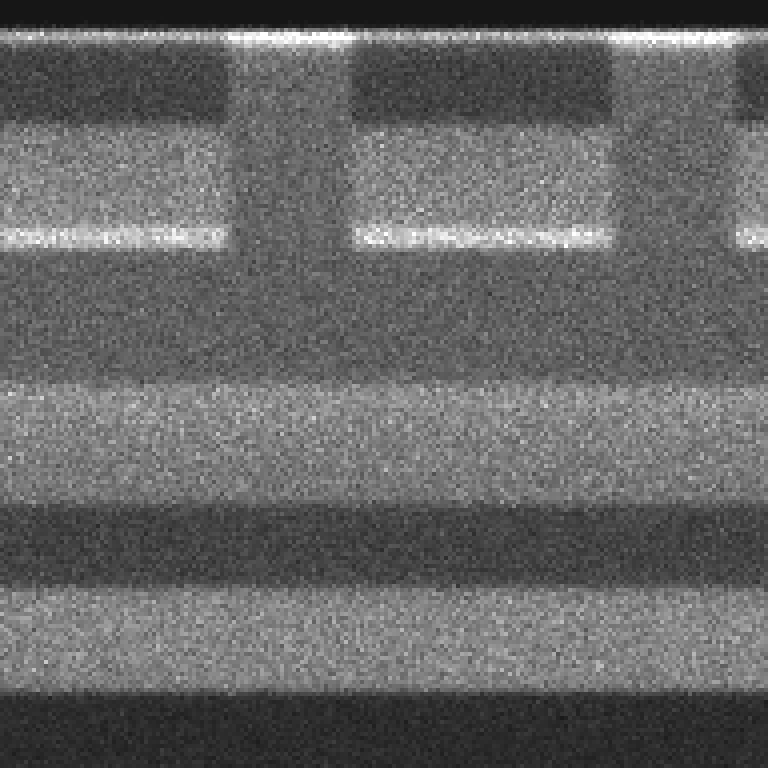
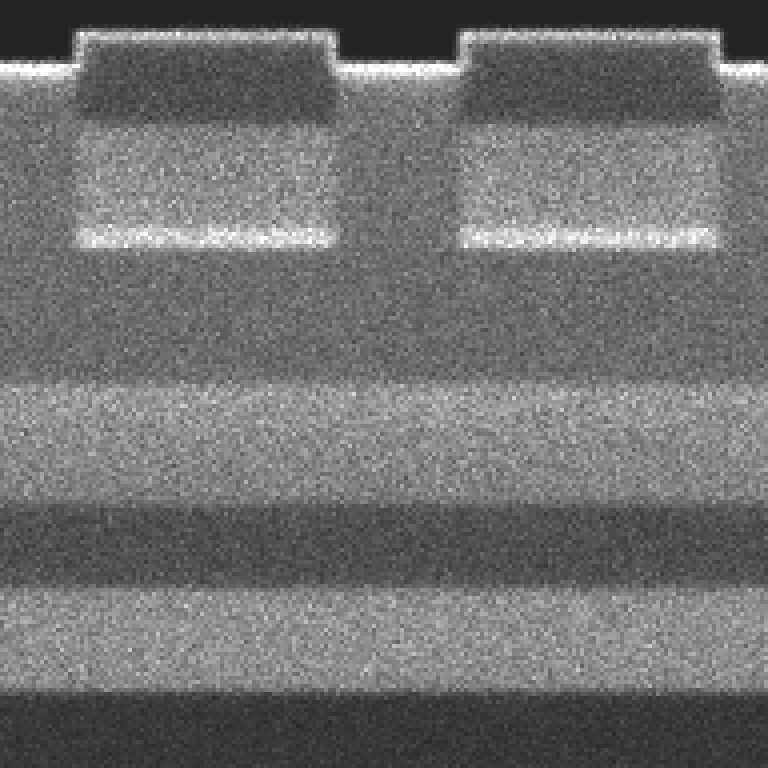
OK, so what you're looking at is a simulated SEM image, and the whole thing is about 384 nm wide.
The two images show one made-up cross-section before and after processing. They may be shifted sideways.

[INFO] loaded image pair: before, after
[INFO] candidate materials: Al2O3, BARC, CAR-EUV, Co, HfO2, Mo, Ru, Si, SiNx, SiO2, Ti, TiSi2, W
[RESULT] removed Al2O3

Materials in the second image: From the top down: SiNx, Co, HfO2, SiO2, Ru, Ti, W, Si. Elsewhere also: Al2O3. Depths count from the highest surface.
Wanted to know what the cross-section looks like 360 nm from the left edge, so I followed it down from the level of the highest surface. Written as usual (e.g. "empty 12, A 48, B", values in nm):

empty 16, Al2O3 92, SiO2 68, Ru 60, Ti 42, W 52, Si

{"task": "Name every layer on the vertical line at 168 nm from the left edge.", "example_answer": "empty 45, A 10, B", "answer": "empty 16, Al2O3 92, SiO2 68, Ru 60, Ti 42, W 52, Si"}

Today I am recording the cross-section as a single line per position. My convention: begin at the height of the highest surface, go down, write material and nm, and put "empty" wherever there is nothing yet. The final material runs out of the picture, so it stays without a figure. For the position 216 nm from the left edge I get empty 16, Al2O3 92, SiO2 68, Ru 60, Ti 42, W 52, Si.